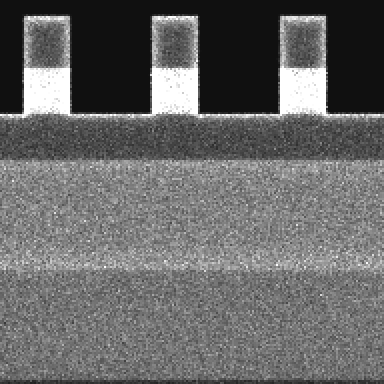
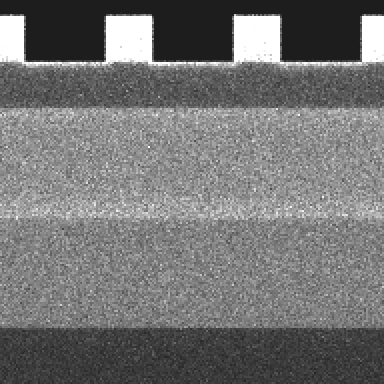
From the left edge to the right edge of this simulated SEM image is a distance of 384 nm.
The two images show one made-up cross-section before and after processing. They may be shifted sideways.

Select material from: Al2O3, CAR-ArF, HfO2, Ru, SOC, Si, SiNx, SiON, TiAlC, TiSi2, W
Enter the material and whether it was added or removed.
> SOC / removed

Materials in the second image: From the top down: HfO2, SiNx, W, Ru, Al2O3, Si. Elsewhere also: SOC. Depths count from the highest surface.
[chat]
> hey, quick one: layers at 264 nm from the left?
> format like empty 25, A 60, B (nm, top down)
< HfO2 46, SiNx 46, W 98, Ru 12, Al2O3 110, Si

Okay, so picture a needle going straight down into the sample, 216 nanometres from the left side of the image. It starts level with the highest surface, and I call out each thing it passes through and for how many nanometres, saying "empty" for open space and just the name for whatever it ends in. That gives empty 46, SiNx 46, W 98, Ru 12, Al2O3 110, Si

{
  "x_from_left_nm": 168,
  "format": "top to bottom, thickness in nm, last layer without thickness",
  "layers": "empty 46, SiNx 46, W 98, Ru 12, Al2O3 110, Si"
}